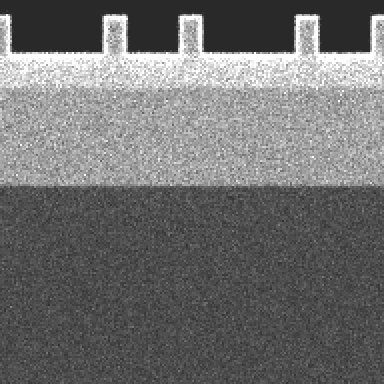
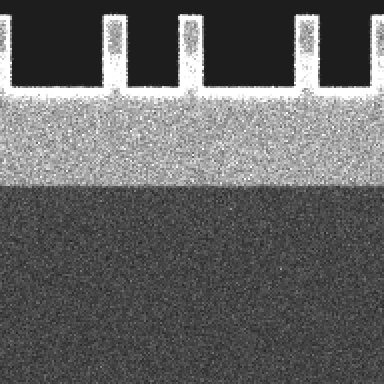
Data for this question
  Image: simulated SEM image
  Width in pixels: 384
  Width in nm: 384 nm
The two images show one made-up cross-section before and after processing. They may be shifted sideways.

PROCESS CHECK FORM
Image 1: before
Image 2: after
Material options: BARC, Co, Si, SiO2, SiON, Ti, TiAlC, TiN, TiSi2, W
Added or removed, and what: removed, Co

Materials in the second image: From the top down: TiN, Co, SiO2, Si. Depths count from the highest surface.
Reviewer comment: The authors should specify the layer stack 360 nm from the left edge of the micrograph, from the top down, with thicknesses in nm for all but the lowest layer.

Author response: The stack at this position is empty 72, SiO2 98, Si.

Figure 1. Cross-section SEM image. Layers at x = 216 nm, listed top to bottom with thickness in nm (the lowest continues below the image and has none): empty 72, SiO2 98, Si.